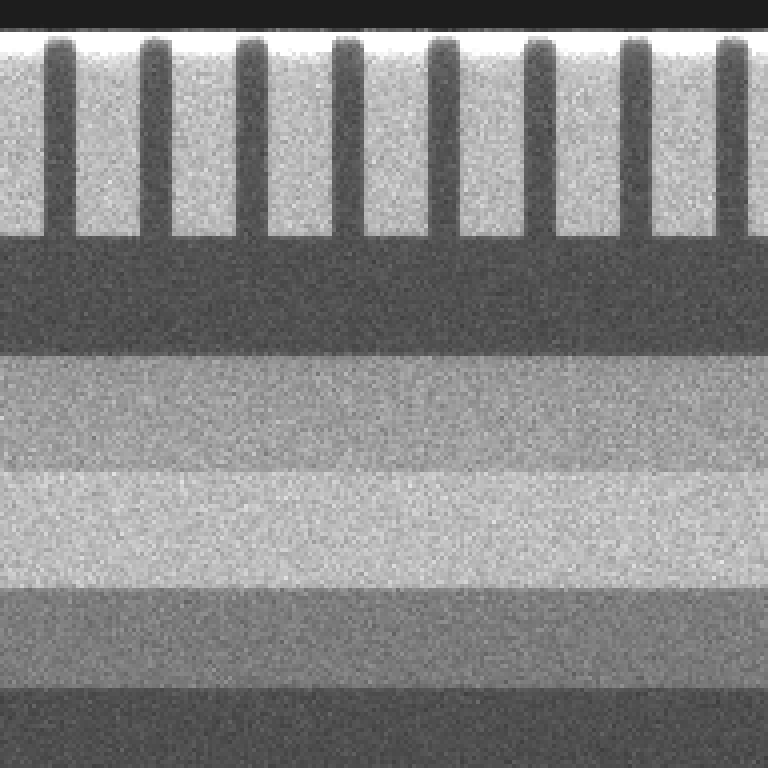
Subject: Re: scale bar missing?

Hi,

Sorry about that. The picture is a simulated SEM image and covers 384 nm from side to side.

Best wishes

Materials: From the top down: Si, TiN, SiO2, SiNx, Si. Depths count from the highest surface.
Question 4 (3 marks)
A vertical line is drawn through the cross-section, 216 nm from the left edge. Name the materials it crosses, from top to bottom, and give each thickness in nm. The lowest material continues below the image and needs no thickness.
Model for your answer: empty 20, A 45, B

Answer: Si 162, TiN 58, SiO2 58, SiNx 50, Si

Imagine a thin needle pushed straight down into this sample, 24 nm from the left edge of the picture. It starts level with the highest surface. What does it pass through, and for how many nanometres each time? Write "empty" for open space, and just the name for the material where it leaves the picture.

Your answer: Si 162, TiN 58, SiO2 58, SiNx 50, Si